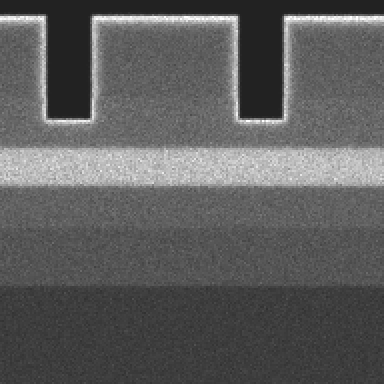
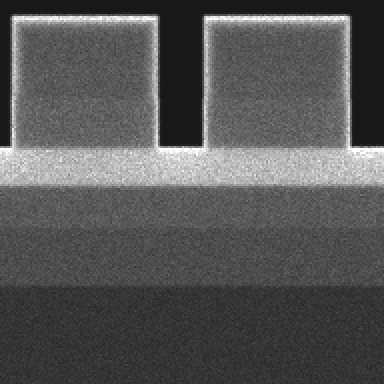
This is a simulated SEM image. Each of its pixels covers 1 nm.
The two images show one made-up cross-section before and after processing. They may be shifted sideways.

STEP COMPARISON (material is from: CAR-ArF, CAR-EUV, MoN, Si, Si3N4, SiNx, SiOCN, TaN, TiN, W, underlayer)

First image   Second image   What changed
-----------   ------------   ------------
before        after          TiN, removed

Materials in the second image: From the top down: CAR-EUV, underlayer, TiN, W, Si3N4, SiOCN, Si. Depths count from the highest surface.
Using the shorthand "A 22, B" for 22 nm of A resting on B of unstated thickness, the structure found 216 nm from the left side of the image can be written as CAR-EUV 48, underlayer 34, TiN 50, W 38, Si3N4 42, SiOCN 58, Si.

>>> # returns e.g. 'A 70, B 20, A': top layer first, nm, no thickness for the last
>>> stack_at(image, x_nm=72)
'CAR-EUV 48, underlayer 34, TiN 50, W 38, Si3N4 42, SiOCN 58, Si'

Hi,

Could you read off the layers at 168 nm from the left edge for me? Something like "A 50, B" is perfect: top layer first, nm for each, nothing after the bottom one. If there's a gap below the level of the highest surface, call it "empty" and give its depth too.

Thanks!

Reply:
empty 132, W 38, Si3N4 42, SiOCN 58, Si